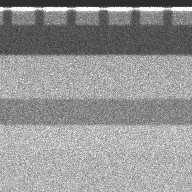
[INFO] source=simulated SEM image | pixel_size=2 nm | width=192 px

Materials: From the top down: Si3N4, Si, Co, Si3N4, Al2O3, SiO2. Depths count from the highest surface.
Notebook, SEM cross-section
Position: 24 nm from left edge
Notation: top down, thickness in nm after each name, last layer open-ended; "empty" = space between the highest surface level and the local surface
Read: Si3N4 34, Si 60, Co 88, Si3N4 52, Al2O3 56, SiO2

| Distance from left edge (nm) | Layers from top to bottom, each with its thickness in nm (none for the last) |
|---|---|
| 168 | Si3N4 34, Si 60, Co 88, Si3N4 52, Al2O3 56, SiO2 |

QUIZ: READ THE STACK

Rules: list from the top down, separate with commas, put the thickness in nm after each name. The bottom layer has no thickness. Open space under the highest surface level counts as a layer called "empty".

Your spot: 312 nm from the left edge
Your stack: Si3N4 34, Si 60, Co 88, Si3N4 52, Al2O3 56, SiO2